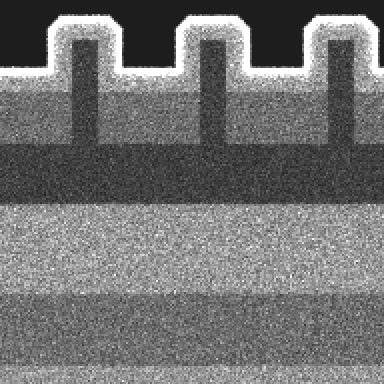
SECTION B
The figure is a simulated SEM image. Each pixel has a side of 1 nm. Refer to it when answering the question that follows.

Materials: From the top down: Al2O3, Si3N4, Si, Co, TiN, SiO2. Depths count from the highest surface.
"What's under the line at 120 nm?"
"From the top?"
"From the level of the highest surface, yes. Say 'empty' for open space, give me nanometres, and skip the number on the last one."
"empty 12, Al2O3 64, Si3N4 52, Si 60, Co 90, TiN 72, SiO2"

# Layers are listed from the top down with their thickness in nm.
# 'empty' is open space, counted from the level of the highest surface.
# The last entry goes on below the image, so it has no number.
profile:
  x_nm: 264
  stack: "empty 52, Al2O3 24, Si3N4 52, Si 60, Co 90, TiN 72, SiO2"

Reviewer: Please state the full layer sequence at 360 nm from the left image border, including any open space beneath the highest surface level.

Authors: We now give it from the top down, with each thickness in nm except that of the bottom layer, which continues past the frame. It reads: Al2O3 76, Si3N4 52, Si 60, Co 90, TiN 72, SiO2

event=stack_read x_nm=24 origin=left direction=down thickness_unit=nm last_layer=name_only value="empty 52, Al2O3 24, Si3N4 52, Si 60, Co 90, TiN 72, SiO2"